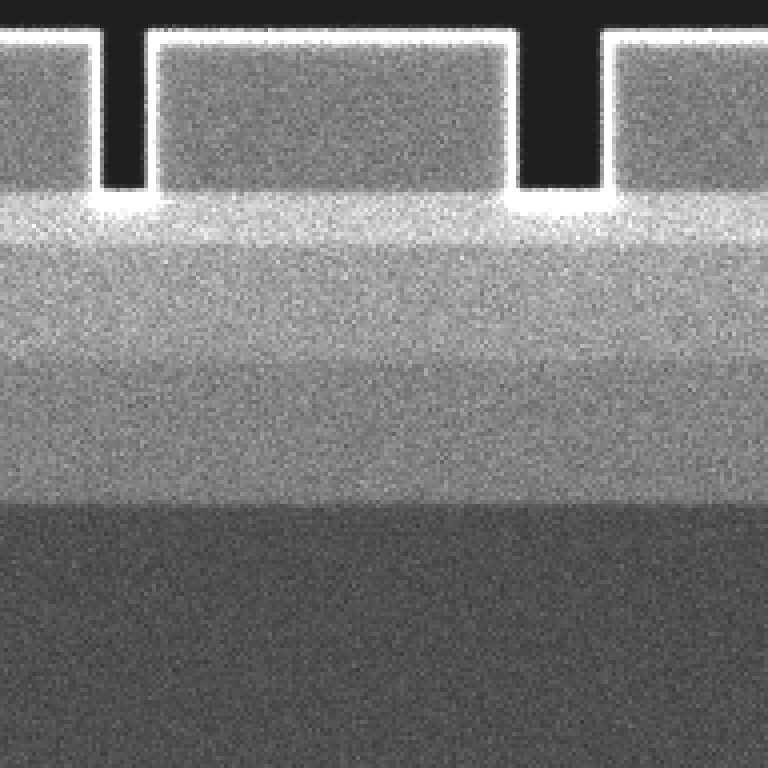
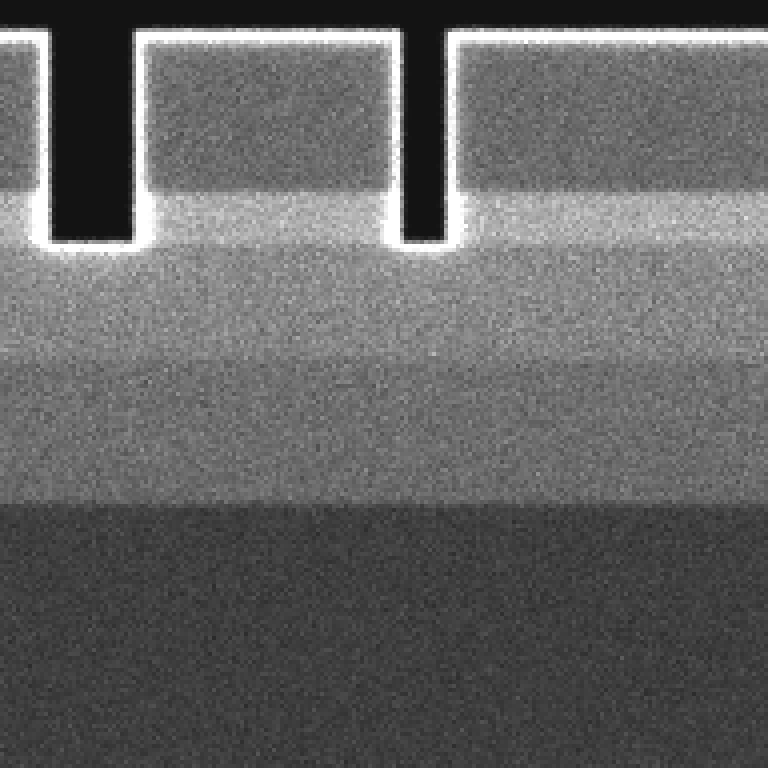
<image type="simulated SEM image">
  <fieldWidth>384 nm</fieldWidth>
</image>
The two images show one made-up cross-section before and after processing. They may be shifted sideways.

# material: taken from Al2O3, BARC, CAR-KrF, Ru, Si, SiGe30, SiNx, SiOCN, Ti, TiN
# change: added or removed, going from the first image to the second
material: Al2O3
change: removed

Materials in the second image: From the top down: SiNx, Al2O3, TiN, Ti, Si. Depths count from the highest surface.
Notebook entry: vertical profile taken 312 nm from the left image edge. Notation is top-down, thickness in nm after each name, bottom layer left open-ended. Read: SiNx 80, Al2O3 26, TiN 58, Ti 72, Si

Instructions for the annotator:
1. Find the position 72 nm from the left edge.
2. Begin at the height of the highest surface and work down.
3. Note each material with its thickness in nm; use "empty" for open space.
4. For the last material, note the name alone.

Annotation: SiNx 80, Al2O3 26, TiN 58, Ti 72, Si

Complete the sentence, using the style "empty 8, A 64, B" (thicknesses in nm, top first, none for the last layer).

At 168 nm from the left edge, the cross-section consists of SiNx 80, Al2O3 26, TiN 58, Ti 72, Si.